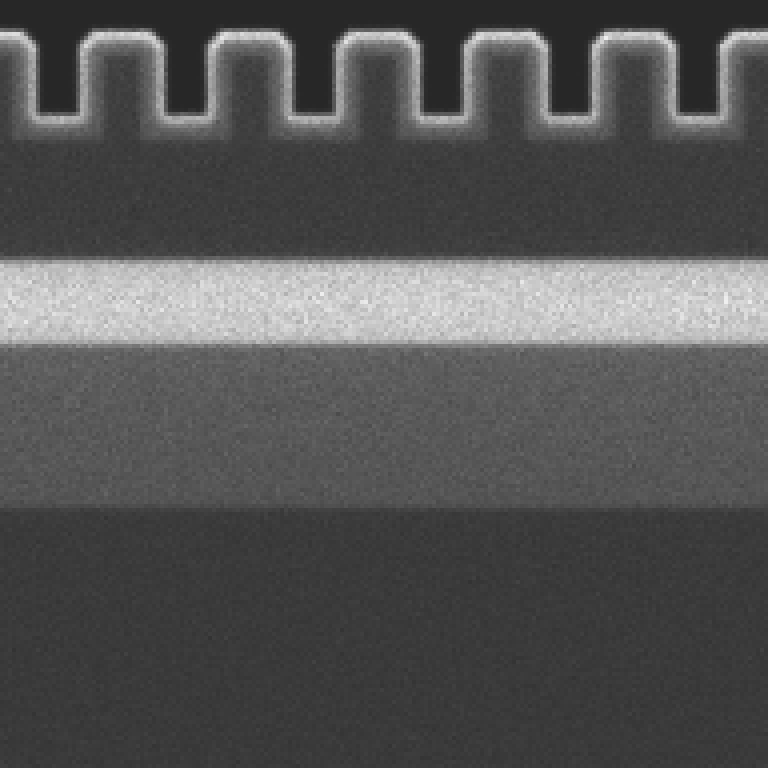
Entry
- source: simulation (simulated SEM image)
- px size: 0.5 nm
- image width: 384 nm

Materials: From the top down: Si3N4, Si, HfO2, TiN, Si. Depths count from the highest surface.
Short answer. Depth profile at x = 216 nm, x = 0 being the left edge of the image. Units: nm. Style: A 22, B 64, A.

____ empty 42, Si3N4 12, Si 60, HfO2 42, TiN 82, Si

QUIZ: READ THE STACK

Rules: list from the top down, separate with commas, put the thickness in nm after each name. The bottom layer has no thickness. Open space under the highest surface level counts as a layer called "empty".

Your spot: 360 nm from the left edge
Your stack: empty 6, Si3N4 48, Si 60, HfO2 42, TiN 82, Si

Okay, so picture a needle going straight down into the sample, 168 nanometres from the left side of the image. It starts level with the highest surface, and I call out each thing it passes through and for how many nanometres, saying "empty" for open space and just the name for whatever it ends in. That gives empty 6, Si3N4 48, Si 60, HfO2 42, TiN 82, Si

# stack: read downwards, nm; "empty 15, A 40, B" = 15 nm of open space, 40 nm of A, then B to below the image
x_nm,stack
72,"Si3N4 54, Si 60, HfO2 42, TiN 82, Si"